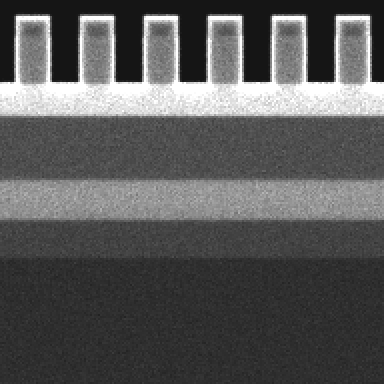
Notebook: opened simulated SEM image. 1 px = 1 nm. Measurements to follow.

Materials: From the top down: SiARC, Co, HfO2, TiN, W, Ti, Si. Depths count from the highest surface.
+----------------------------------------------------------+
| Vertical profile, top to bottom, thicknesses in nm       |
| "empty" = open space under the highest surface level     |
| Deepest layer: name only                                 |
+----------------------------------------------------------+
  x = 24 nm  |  SiARC 20, Co 48, HfO2 32, TiN 64, W 40, Ti 38, Si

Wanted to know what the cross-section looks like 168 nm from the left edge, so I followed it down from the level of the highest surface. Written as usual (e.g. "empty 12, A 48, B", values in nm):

SiARC 20, Co 48, HfO2 32, TiN 64, W 40, Ti 38, Si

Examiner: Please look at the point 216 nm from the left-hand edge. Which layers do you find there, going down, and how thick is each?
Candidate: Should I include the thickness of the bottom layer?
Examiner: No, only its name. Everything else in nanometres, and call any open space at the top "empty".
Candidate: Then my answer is SiARC 20, Co 48, HfO2 32, TiN 64, W 40, Ti 38, Si